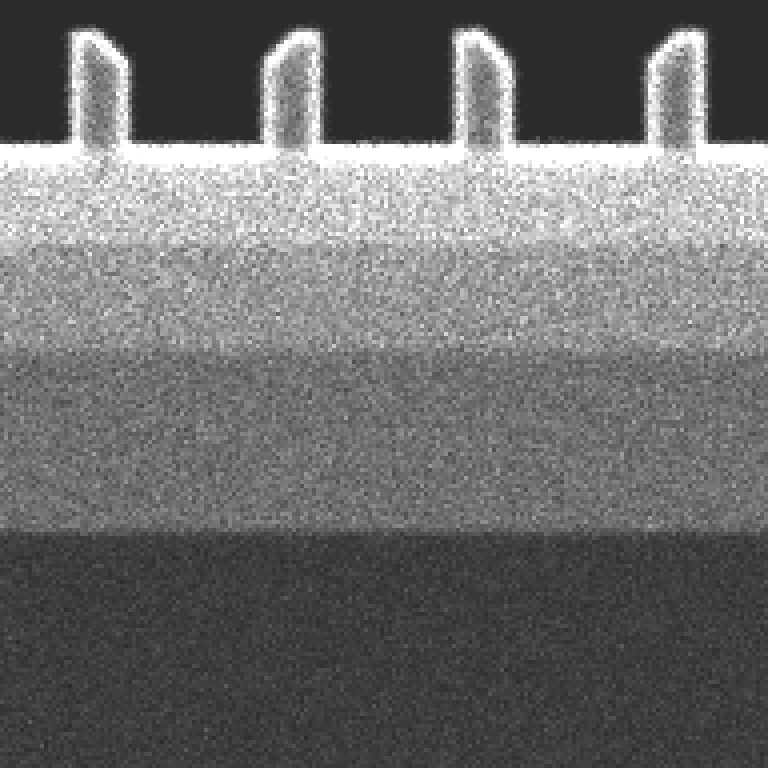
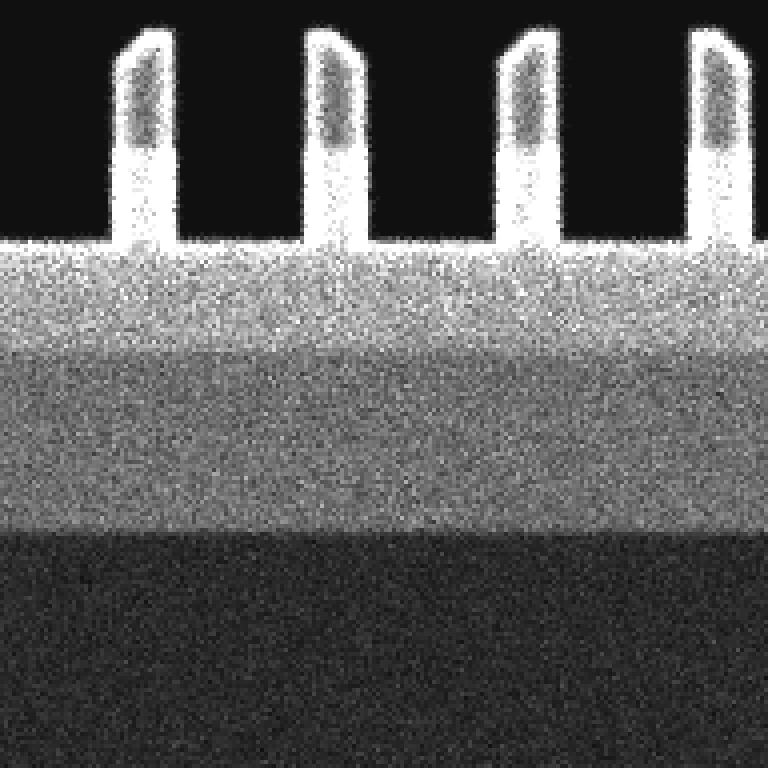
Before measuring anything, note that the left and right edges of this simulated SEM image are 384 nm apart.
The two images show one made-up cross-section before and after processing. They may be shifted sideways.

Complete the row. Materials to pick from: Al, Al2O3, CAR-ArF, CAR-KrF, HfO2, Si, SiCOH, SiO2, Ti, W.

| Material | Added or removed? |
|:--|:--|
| HfO2 | removed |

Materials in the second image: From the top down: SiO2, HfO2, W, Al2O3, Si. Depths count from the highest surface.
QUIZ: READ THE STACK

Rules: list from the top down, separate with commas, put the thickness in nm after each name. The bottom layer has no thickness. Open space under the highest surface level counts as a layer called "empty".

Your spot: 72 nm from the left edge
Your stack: SiO2 58, HfO2 48, W 54, Al2O3 90, Si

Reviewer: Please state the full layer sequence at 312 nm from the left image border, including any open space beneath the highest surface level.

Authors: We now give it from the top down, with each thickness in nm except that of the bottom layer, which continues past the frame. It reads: empty 106, W 54, Al2O3 90, Si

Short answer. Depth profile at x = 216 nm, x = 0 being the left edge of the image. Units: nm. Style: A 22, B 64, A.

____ empty 106, W 54, Al2O3 90, Si